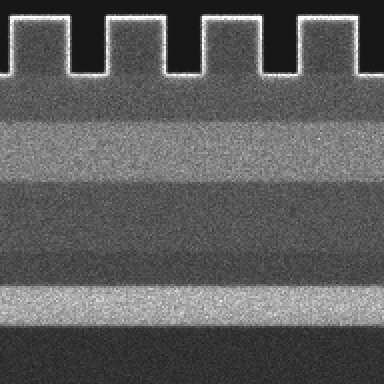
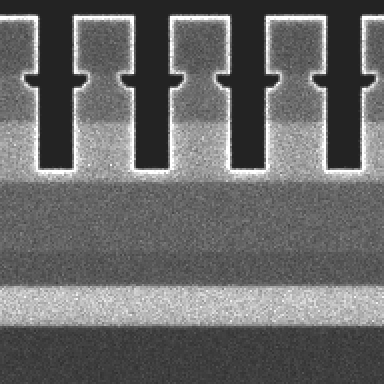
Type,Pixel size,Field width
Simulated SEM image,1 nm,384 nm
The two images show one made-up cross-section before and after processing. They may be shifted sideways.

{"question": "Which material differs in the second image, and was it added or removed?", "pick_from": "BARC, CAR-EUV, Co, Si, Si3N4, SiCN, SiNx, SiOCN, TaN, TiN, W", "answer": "Co and TiN, removed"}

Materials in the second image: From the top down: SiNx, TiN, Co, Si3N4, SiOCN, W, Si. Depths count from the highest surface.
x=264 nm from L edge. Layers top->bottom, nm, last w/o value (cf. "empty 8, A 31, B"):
empty 154, Co 12, Si3N4 70, SiOCN 34, W 40, Si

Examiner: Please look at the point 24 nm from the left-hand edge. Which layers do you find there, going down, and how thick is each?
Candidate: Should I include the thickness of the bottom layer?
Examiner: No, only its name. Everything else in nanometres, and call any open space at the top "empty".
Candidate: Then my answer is SiNx 58, empty 8, TiN 40, Co 60, Si3N4 70, SiOCN 34, W 40, Si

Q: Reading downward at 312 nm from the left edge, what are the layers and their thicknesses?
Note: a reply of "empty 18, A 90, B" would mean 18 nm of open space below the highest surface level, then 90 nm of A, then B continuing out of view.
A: SiNx 58, empty 8, TiN 40, Co 60, Si3N4 70, SiOCN 34, W 40, Si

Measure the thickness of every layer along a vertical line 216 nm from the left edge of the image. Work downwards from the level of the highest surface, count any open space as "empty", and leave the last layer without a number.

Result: SiNx 58, empty 8, TiN 40, Co 60, Si3N4 70, SiOCN 34, W 40, Si